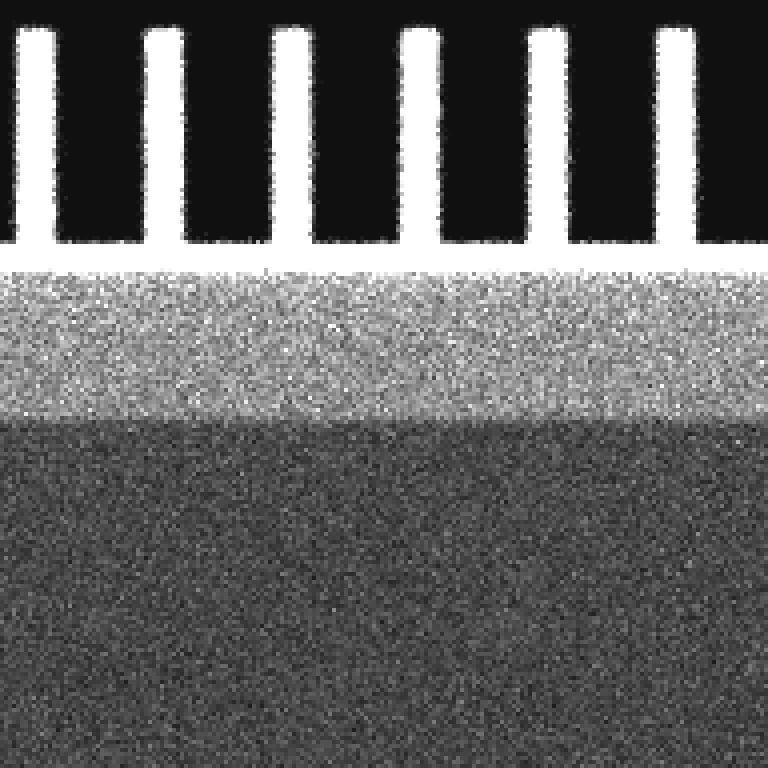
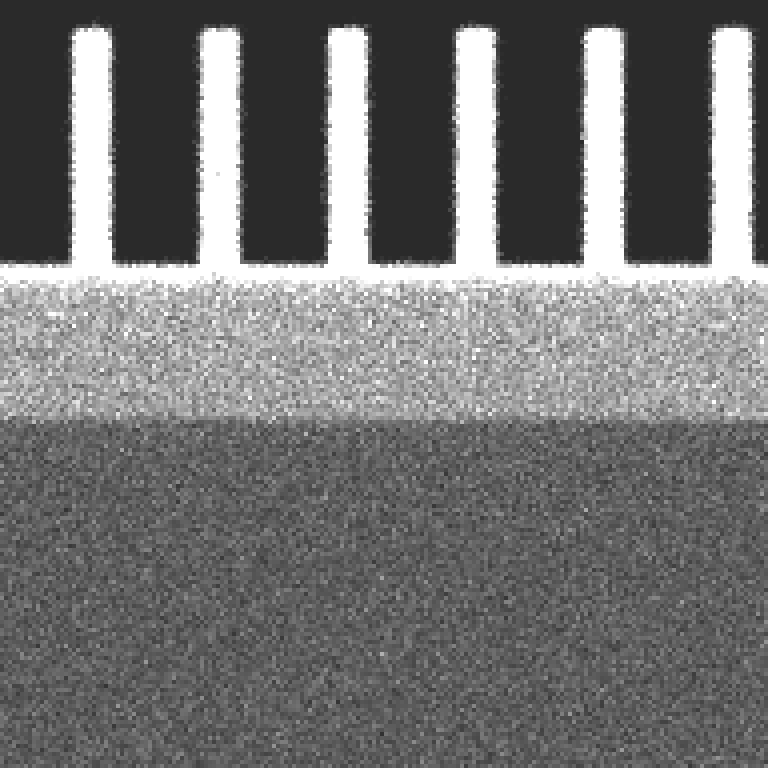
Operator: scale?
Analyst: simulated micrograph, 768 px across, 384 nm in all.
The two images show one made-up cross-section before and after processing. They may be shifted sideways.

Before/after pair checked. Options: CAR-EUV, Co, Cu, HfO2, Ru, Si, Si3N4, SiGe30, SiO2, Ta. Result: removed HfO2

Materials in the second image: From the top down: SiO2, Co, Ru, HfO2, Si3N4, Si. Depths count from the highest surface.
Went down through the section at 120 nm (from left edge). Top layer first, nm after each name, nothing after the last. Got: empty 118, Si3N4 76, Si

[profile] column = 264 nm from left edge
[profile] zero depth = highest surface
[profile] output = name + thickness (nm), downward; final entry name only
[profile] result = empty 118, Si3N4 76, Si